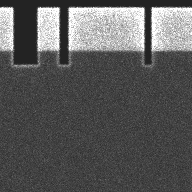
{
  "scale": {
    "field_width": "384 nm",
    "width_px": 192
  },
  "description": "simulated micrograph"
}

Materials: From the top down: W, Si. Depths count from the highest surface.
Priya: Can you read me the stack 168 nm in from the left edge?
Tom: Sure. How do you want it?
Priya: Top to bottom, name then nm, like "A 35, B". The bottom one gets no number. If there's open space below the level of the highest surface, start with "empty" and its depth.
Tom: W 86, Si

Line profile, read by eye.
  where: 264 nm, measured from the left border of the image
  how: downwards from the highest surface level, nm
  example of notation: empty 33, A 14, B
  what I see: W 86, Si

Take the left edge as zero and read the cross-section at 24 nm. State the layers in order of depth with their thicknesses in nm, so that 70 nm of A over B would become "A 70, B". W 86, Si